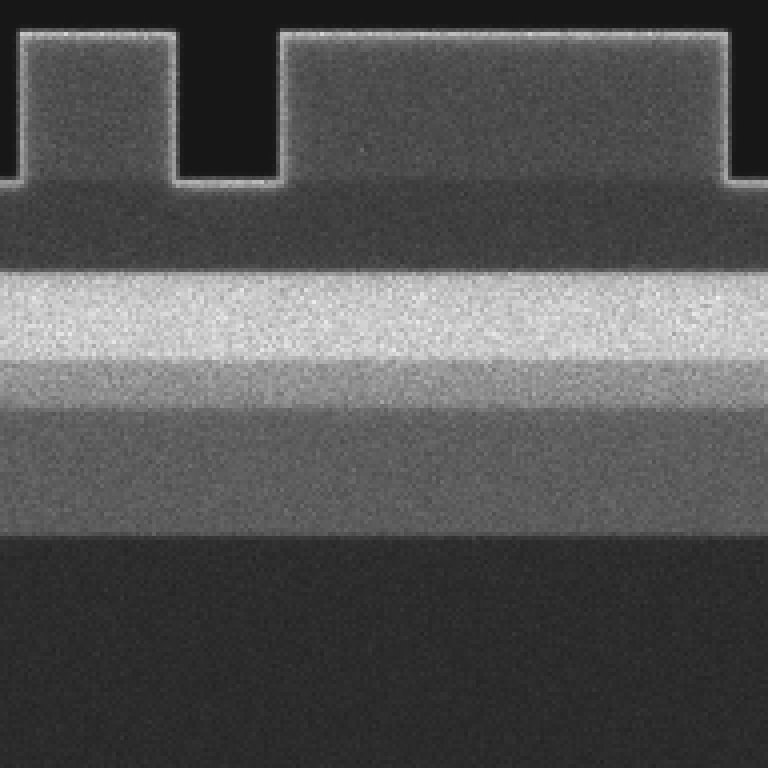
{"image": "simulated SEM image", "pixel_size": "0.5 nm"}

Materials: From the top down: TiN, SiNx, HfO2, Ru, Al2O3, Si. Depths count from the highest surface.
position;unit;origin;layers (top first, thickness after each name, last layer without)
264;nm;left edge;TiN 74, SiNx 46, HfO2 44, Ru 24, Al2O3 64, Si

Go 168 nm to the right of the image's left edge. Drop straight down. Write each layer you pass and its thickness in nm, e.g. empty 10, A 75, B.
TiN 74, SiNx 46, HfO2 44, Ru 24, Al2O3 64, Si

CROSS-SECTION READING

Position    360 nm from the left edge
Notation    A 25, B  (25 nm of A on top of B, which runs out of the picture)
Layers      TiN 74, SiNx 46, HfO2 44, Ru 24, Al2O3 64, Si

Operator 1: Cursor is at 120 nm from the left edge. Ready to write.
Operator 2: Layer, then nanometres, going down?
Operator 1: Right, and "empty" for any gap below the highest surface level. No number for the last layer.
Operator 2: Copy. empty 74, SiNx 46, HfO2 44, Ru 24, Al2O3 64, Si